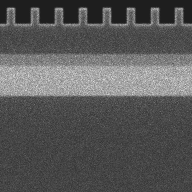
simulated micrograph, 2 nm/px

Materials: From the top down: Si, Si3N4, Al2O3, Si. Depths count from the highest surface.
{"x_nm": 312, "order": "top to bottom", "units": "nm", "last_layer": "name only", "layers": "Si 92, Si3N4 24, Al2O3 60, Si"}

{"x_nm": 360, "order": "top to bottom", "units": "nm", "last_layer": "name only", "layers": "Si 92, Si3N4 24, Al2O3 60, Si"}